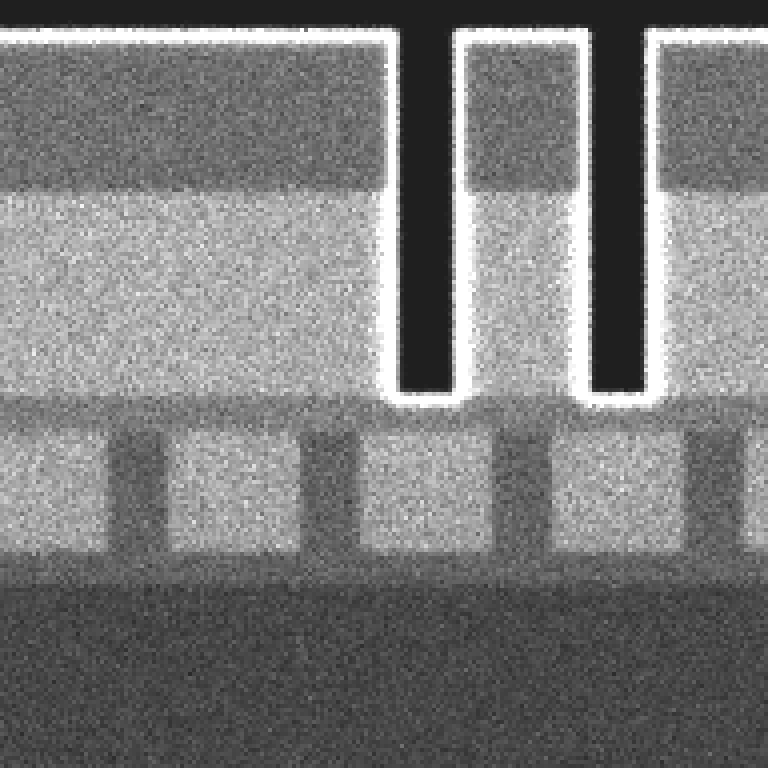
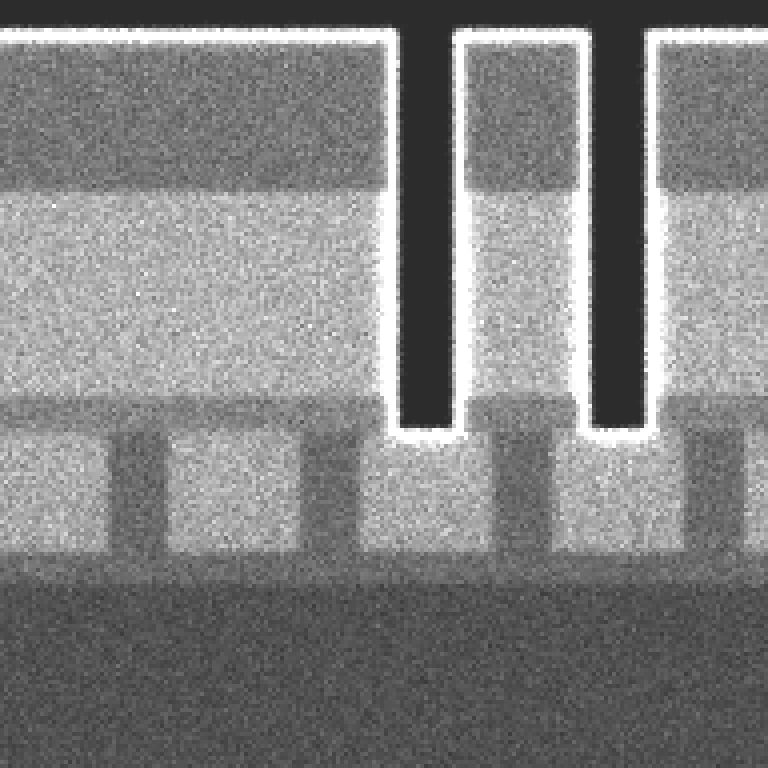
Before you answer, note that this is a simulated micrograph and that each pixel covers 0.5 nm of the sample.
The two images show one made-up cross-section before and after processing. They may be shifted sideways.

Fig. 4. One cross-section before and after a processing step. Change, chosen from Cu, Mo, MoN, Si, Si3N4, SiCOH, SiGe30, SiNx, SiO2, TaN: Si3N4 removed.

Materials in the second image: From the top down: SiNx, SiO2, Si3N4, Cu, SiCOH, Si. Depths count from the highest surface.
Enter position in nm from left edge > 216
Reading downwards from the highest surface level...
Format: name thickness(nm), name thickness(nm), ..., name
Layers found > empty 200, Cu 60, SiCOH 16, Si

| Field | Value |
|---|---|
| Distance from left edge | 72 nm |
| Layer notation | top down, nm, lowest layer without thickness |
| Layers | SiNx 80, SiO2 102, Si3N4 18, SiCOH 76, Si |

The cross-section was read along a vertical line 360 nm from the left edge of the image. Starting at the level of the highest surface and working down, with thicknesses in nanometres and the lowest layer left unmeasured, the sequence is SiNx 80, SiO2 102, Si3N4 18, SiCOH 76, Si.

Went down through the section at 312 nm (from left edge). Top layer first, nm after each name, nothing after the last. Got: empty 200, Cu 60, SiCOH 16, Si